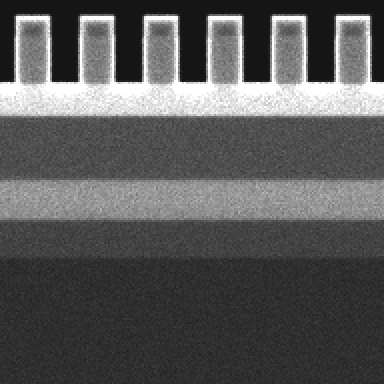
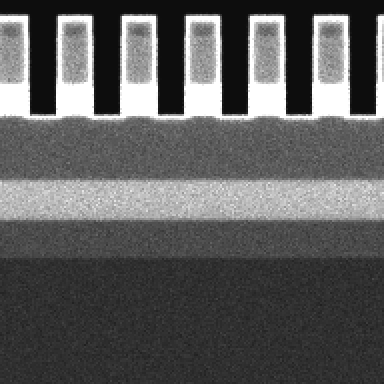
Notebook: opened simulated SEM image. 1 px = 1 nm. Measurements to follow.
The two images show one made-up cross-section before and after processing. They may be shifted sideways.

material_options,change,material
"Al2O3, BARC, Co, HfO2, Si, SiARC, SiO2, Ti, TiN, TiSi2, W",removed,HfO2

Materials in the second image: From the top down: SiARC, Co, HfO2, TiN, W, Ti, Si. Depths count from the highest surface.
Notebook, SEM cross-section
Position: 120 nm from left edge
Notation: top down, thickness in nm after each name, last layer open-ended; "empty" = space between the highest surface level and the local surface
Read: empty 100, TiN 64, W 40, Ti 38, Si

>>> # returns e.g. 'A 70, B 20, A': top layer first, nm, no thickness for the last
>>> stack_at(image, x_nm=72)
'SiARC 20, Co 48, HfO2 32, TiN 64, W 40, Ti 38, Si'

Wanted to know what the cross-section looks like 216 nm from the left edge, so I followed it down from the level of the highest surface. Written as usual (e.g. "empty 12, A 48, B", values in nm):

SiARC 20, Co 48, HfO2 32, TiN 64, W 40, Ti 38, Si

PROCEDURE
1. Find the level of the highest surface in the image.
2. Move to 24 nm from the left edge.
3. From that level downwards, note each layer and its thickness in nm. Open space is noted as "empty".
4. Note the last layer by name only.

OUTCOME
SiARC 20, Co 48, HfO2 32, TiN 64, W 40, Ti 38, Si